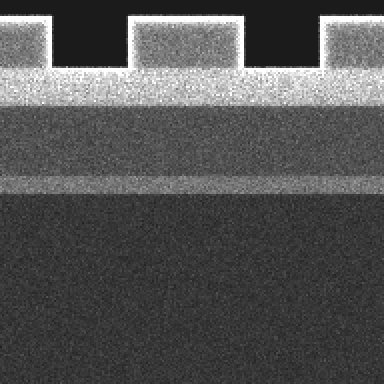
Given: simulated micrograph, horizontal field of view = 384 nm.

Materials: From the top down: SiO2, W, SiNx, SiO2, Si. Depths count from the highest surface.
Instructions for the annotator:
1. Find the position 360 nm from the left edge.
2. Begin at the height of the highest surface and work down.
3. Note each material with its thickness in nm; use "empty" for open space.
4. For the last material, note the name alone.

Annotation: SiO2 52, W 38, SiNx 70, SiO2 18, Si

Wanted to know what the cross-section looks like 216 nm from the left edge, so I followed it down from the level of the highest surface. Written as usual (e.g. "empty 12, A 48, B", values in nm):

SiO2 52, W 38, SiNx 70, SiO2 18, Si